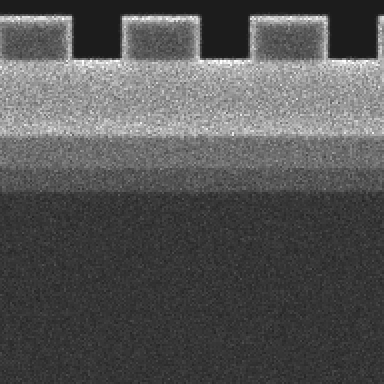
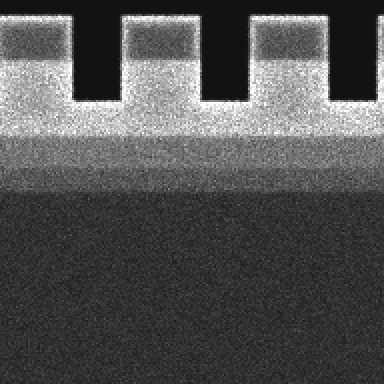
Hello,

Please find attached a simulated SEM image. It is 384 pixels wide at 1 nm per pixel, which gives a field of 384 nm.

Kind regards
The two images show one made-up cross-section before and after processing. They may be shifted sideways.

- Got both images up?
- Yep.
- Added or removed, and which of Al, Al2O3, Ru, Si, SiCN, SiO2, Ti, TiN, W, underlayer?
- removed, W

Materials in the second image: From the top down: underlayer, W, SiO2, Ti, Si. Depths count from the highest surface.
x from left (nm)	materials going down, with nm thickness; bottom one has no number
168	underlayer 44, W 76, SiO2 32, Ti 24, Si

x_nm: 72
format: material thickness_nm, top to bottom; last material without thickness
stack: empty 86, W 34, SiO2 32, Ti 24, Si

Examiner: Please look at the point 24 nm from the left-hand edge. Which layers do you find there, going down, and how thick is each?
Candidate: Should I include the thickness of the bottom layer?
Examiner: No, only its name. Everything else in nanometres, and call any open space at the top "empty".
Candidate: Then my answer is underlayer 44, W 76, SiO2 32, Ti 24, Si